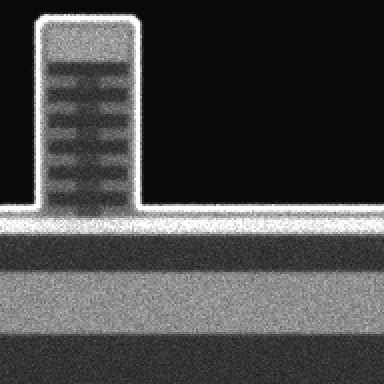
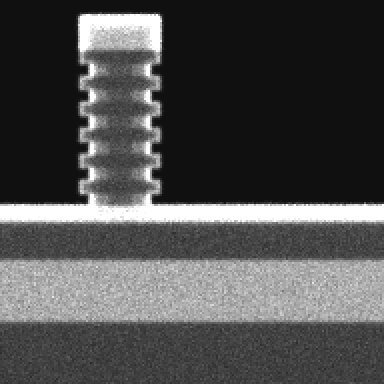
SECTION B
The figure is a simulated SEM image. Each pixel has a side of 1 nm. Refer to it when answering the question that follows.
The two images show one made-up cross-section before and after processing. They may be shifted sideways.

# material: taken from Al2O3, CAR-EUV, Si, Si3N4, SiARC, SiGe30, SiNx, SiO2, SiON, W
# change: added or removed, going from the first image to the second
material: Si3N4
change: removed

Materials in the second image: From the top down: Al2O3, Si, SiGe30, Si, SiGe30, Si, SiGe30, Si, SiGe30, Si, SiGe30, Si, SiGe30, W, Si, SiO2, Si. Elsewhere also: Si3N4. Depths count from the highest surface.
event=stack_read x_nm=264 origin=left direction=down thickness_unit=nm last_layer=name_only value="empty 190, W 16, Si 38, SiO2 62, Si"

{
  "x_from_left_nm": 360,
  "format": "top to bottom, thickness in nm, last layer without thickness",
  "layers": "empty 190, W 16, Si 38, SiO2 62, Si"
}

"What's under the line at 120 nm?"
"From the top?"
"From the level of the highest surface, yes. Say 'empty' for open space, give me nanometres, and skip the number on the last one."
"Al2O3 34, Si 14, SiGe30 12, Si 14, SiGe30 12, Si 14, SiGe30 12, Si 14, SiGe30 12, Si 14, SiGe30 12, Si 14, SiGe30 12, W 16, Si 38, SiO2 62, Si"